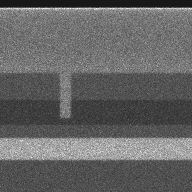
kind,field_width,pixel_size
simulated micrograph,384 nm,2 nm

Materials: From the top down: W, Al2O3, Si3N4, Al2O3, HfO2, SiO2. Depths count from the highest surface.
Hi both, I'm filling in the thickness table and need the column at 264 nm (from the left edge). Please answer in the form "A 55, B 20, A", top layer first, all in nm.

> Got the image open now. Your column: W 130, Al2O3 54, Si3N4 50, Al2O3 26, HfO2 44, SiO2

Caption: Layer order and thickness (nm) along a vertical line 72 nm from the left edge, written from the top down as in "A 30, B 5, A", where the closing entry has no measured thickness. W 130, Al2O3 54, Si3N4 50, Al2O3 26, HfO2 44, SiO2